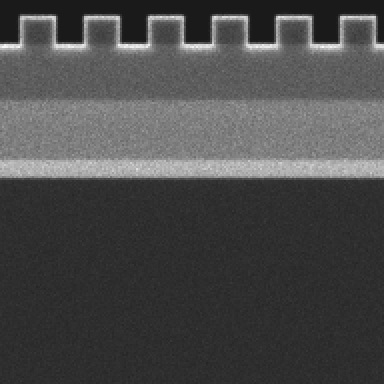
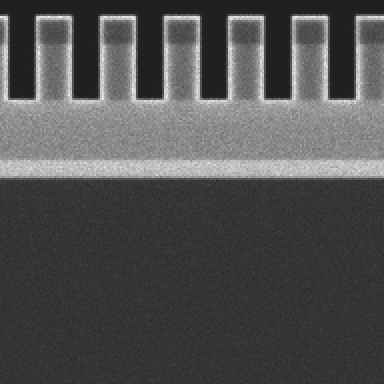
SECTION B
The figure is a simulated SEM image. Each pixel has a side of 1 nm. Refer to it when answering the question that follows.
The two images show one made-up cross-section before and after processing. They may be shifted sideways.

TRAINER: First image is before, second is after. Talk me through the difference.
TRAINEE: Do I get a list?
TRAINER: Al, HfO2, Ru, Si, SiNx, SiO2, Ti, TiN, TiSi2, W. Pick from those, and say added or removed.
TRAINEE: removed: SiO2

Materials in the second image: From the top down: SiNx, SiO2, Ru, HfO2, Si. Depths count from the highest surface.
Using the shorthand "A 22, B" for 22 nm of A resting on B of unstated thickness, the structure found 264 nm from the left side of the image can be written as empty 84, Ru 60, HfO2 18, Si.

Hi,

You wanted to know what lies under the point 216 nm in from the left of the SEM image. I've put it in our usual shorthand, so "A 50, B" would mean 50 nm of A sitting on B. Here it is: empty 84, Ru 60, HfO2 18, Si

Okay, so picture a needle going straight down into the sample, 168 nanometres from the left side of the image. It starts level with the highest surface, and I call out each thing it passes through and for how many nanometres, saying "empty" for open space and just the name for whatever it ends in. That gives SiNx 28, SiO2 56, Ru 60, HfO2 18, Si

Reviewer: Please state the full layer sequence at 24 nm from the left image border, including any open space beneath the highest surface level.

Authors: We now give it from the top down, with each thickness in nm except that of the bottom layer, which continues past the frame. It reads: empty 84, Ru 60, HfO2 18, Si